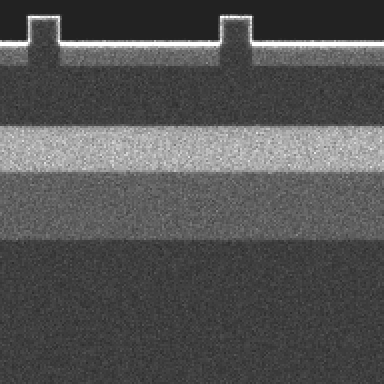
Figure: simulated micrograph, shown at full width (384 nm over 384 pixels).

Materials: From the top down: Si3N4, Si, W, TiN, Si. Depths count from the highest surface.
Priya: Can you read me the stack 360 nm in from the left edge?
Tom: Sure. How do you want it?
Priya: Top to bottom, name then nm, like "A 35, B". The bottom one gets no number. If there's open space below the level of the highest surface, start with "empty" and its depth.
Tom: empty 26, Si3N4 24, Si 60, W 46, TiN 68, Si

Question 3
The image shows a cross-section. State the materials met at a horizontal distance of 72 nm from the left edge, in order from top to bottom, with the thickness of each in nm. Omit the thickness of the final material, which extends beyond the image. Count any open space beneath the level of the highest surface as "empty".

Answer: empty 26, Si3N4 24, Si 60, W 46, TiN 68, Si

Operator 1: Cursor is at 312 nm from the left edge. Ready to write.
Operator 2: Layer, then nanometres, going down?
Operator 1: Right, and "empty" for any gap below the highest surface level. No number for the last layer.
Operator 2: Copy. empty 26, Si3N4 24, Si 60, W 46, TiN 68, Si